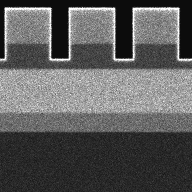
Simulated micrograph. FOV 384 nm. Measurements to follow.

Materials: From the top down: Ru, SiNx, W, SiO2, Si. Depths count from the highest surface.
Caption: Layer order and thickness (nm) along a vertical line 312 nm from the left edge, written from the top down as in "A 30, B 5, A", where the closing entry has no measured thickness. Ru 72, SiNx 50, W 88, SiO2 38, Si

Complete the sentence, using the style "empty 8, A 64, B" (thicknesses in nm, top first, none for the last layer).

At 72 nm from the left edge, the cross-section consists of Ru 72, SiNx 50, W 88, SiO2 38, Si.